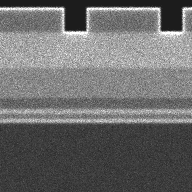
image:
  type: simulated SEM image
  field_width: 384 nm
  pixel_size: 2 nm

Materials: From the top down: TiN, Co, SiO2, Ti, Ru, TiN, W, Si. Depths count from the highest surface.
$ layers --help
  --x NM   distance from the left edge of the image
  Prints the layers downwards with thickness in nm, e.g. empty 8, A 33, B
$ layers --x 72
TiN 48, Co 72, SiO2 60, Ti 22, Ru 10, TiN 10, W 8, Si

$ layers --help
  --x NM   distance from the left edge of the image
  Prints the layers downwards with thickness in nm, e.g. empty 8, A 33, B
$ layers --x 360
empty 48, Co 72, SiO2 60, Ti 22, Ru 10, TiN 10, W 8, Si